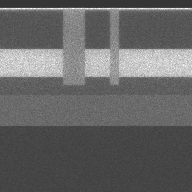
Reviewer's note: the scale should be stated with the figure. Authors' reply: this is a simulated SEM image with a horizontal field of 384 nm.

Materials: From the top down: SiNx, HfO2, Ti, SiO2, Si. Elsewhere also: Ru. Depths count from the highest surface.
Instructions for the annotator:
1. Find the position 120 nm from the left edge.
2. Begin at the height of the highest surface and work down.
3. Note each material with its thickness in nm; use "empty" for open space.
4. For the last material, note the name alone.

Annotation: SiNx 82, HfO2 56, Ti 36, SiO2 62, Si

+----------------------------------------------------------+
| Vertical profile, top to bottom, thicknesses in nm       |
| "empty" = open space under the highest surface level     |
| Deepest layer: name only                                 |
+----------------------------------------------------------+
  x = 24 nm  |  SiNx 82, HfO2 56, Ti 36, SiO2 62, Si